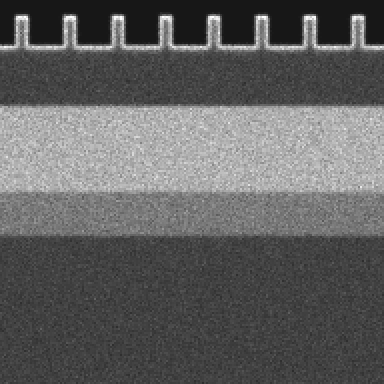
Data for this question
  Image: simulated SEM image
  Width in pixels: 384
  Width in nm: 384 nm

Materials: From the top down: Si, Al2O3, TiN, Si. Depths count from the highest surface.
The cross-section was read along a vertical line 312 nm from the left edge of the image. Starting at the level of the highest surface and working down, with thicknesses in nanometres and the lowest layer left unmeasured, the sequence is Si 90, Al2O3 86, TiN 44, Si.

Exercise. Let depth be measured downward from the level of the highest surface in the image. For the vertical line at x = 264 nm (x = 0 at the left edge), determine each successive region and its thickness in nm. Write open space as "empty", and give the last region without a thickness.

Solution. Si 90, Al2O3 86, TiN 44, Si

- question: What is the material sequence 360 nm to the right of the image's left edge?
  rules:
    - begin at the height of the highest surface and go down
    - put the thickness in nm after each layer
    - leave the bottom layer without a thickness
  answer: Si 90, Al2O3 86, TiN 44, Si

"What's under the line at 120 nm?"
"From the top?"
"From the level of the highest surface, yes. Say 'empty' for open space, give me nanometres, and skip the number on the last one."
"Si 90, Al2O3 86, TiN 44, Si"